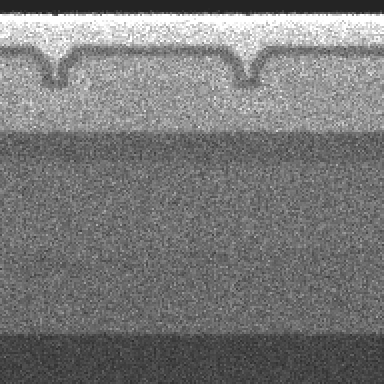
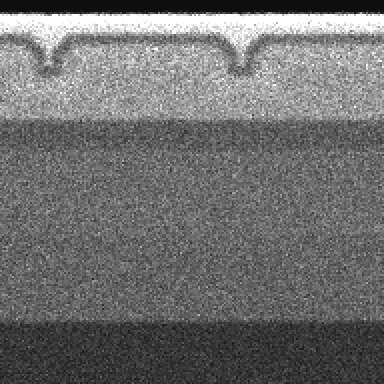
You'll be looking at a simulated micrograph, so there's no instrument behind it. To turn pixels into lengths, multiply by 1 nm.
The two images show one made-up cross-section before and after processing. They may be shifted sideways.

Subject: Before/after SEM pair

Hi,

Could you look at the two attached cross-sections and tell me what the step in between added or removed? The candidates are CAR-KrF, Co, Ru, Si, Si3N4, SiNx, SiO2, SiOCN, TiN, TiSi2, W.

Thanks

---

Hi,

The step removed W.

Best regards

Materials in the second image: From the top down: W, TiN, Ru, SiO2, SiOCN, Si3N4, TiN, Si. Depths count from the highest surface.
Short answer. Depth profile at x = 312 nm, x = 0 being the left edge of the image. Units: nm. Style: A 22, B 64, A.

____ W 18, TiN 10, Ru 24, SiO2 52, SiOCN 30, Si3N4 86, TiN 86, Si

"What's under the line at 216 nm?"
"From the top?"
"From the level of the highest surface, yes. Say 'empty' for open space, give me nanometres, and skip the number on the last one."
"W 18, TiN 12, Ru 54, SiO2 20, SiOCN 30, Si3N4 86, TiN 86, Si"